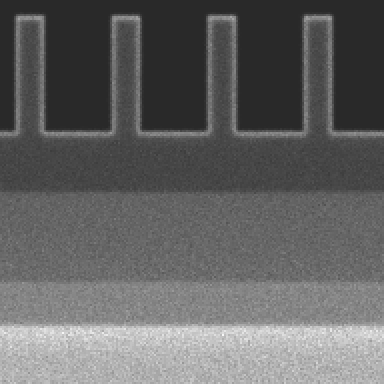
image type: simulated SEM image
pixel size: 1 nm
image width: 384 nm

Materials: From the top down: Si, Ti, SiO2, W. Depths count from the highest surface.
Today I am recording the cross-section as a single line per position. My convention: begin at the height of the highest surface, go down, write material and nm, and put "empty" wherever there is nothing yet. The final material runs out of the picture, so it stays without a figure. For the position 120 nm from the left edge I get Si 176, Ti 90, SiO2 44, W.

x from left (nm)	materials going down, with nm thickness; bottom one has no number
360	empty 116, Si 60, Ti 90, SiO2 44, W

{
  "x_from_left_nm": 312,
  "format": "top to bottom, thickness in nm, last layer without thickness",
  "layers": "Si 176, Ti 90, SiO2 44, W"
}